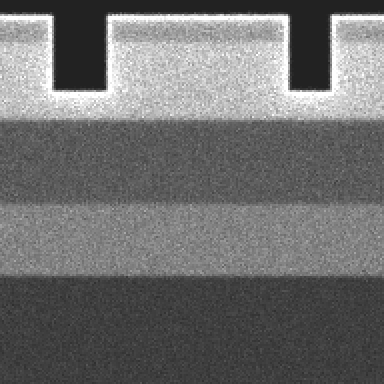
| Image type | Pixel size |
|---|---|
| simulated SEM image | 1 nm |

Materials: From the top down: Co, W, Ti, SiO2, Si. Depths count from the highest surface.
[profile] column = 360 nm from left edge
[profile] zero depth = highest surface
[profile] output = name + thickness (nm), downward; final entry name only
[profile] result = Co 26, W 78, Ti 84, SiO2 72, Si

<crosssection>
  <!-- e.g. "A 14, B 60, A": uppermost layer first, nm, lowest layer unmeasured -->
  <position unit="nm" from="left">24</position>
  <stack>Co 26, W 78, Ti 84, SiO2 72, Si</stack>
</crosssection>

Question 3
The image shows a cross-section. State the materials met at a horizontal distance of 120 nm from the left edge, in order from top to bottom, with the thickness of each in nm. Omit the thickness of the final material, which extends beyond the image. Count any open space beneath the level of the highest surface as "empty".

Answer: Co 26, W 78, Ti 84, SiO2 72, Si